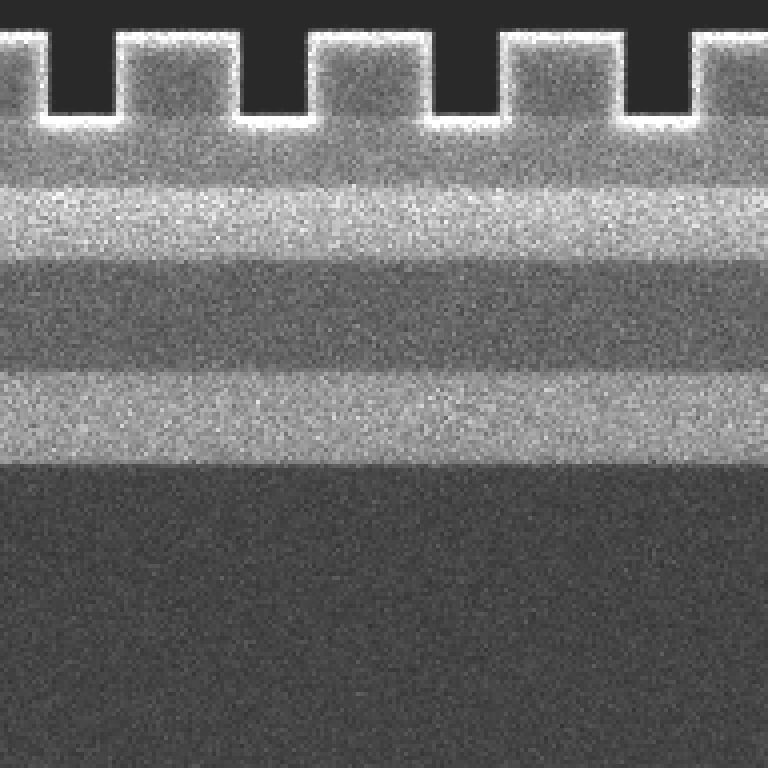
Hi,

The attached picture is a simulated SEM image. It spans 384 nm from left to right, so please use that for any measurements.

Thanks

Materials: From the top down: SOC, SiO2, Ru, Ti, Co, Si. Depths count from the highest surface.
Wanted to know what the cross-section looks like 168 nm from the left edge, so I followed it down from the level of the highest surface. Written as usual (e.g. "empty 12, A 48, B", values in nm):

SOC 42, SiO2 36, Ru 36, Ti 56, Co 46, Si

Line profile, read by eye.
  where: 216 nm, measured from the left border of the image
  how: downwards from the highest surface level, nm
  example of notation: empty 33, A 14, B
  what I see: empty 42, SiO2 36, Ru 36, Ti 56, Co 46, Si